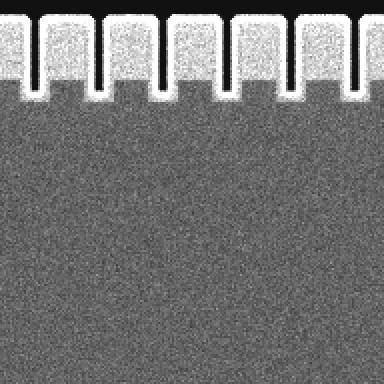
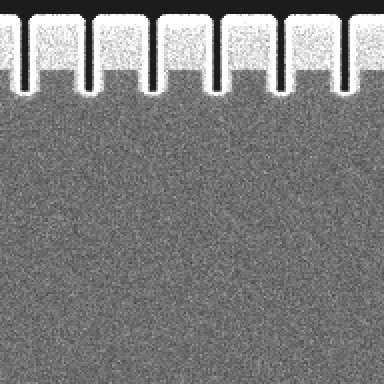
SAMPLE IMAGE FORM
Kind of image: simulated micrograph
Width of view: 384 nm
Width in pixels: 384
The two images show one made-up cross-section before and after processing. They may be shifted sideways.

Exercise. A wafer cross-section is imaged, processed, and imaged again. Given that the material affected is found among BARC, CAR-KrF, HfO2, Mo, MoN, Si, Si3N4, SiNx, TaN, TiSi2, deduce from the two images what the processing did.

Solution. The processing removed SiNx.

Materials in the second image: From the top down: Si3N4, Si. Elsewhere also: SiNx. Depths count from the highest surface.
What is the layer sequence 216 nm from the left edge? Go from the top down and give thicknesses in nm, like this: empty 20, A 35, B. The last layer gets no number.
empty 76, Si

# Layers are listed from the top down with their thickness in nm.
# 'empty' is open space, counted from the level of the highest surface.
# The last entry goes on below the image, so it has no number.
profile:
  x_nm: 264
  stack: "Si3N4 54, Si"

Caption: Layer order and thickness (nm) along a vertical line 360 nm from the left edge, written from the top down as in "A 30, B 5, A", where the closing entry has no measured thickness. Si3N4 54, Si